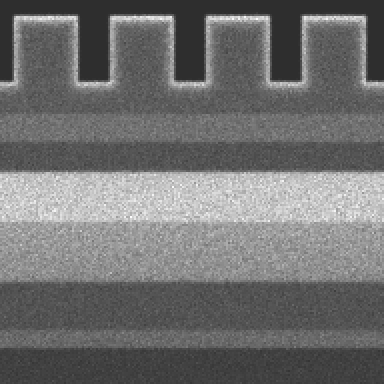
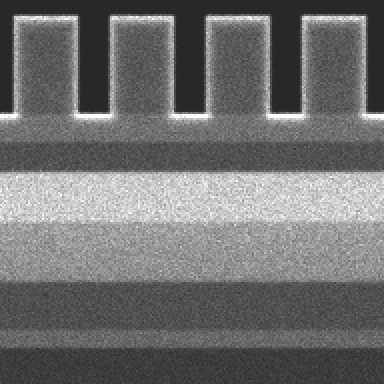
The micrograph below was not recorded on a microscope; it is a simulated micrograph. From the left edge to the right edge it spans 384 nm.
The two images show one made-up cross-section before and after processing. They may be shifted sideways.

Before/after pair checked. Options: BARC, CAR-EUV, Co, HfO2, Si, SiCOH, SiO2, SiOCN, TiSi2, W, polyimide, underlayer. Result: removed underlayer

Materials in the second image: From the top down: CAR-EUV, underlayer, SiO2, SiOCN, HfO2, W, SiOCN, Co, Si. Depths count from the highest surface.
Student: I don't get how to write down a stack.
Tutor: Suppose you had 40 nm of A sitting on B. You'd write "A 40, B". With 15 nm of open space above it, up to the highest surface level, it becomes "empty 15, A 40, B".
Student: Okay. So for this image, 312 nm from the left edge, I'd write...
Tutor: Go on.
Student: CAR-EUV 66, underlayer 32, SiO2 28, SiOCN 30, HfO2 50, W 60, SiOCN 48, Co 18, Si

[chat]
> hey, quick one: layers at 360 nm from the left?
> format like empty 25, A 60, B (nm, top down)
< CAR-EUV 66, underlayer 32, SiO2 28, SiOCN 30, HfO2 50, W 60, SiOCN 48, Co 18, Si